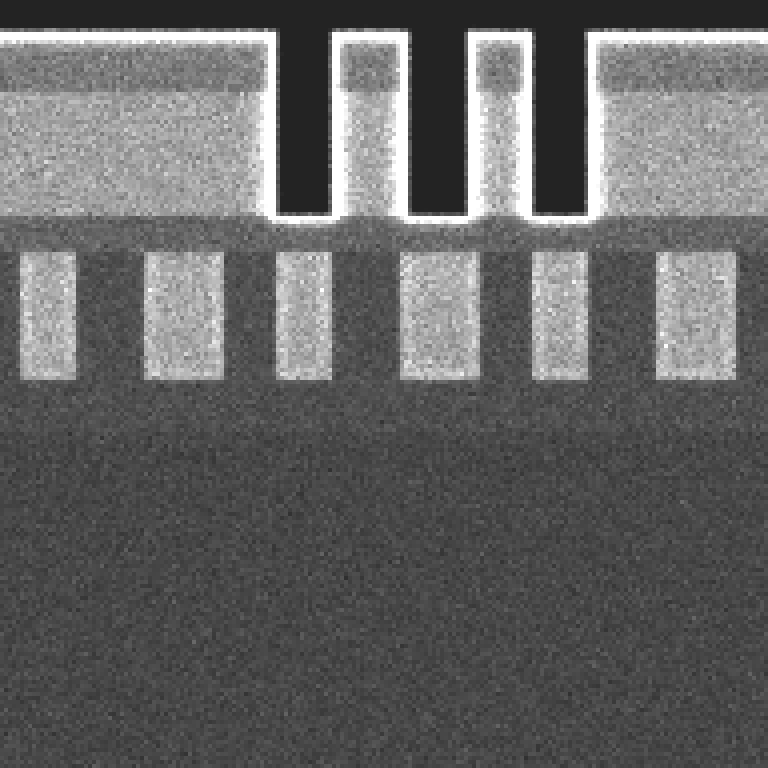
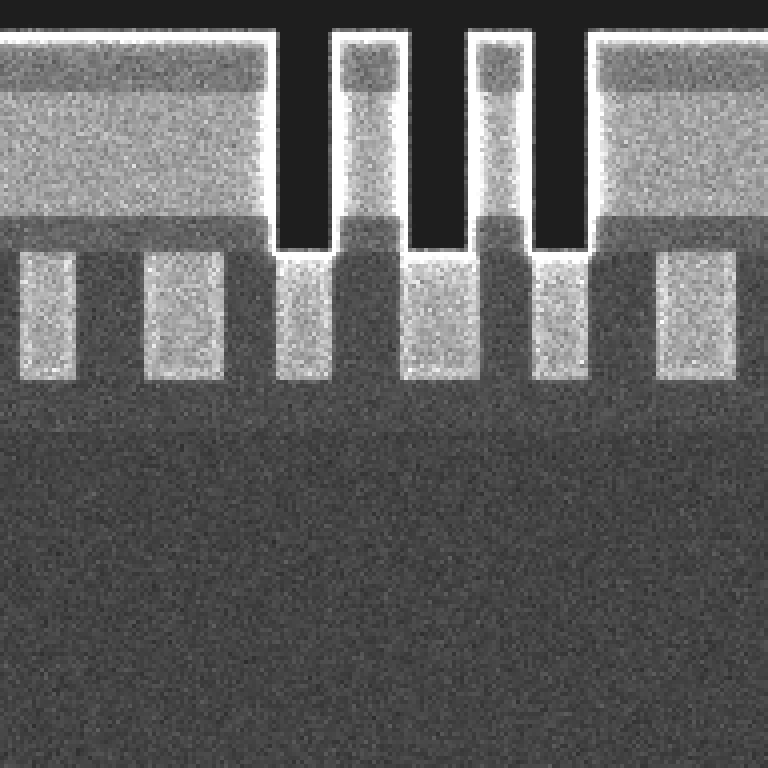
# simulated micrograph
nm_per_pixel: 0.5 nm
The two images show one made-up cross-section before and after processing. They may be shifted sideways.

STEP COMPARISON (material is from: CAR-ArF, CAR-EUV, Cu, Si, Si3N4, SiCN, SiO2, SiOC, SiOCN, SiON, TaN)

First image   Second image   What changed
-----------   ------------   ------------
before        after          SiCN, removed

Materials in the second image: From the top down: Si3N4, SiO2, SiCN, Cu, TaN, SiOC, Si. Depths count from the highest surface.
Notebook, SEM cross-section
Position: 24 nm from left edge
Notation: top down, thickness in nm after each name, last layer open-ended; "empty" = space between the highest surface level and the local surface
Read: Si3N4 30, SiO2 62, SiCN 18, Cu 58, TaN 6, SiOC 26, Si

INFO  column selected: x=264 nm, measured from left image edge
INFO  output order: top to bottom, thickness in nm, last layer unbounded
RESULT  Si3N4 30, SiO2 62, SiCN 18, SiOC 90, Si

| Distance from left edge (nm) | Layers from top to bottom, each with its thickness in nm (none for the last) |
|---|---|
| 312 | Si3N4 30, SiO2 62, SiCN 18, SiOC 90, Si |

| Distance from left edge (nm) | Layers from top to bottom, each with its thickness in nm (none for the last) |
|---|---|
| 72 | Si3N4 30, SiO2 62, SiCN 18, TaN 64, SiOC 26, Si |